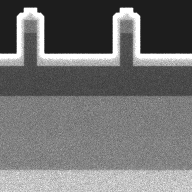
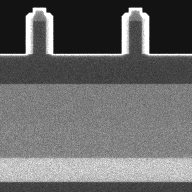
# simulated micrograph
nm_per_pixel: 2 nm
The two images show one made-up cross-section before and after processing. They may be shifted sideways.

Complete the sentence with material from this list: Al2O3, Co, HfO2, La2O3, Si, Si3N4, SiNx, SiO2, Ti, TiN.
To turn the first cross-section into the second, SiO2 must be removed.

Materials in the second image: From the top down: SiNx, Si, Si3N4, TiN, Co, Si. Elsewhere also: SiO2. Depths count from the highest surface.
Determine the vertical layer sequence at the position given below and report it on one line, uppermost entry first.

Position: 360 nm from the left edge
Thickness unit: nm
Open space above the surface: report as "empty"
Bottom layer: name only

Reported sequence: empty 92, Si 60, Si3N4 78, TiN 70, Co 48, Si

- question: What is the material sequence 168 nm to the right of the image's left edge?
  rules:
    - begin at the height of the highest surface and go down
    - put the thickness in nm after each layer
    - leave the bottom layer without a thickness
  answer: empty 92, Si 60, Si3N4 78, TiN 70, Co 48, Si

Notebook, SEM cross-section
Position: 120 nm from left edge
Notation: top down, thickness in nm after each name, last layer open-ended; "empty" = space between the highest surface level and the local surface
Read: empty 92, Si 60, Si3N4 78, TiN 70, Co 48, Si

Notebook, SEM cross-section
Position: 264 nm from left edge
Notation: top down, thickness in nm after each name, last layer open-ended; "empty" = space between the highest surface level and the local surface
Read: SiNx 26, Si 126, Si3N4 78, TiN 70, Co 48, Si